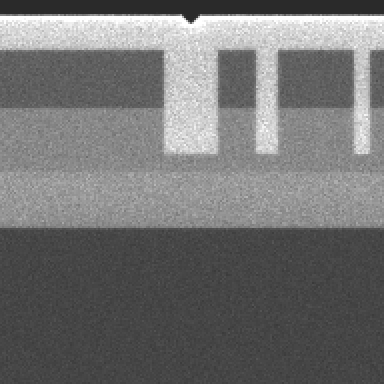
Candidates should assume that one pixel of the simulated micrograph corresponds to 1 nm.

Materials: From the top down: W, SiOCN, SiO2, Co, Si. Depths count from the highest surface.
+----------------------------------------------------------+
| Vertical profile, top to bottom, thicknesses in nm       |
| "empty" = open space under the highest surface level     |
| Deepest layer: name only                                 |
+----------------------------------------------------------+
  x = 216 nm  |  W 138, SiO2 18, Co 56, Si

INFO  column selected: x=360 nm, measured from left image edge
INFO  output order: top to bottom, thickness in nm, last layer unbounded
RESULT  W 138, SiO2 18, Co 56, Si